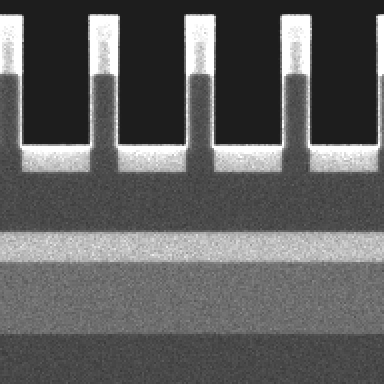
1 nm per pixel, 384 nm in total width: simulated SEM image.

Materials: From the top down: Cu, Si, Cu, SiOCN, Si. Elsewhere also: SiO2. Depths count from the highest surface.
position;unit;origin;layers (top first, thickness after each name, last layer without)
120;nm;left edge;empty 130, Cu 26, Si 60, Cu 30, SiOCN 72, Si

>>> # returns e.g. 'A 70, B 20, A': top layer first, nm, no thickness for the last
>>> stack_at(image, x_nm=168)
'empty 130, Cu 26, Si 60, Cu 30, SiOCN 72, Si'